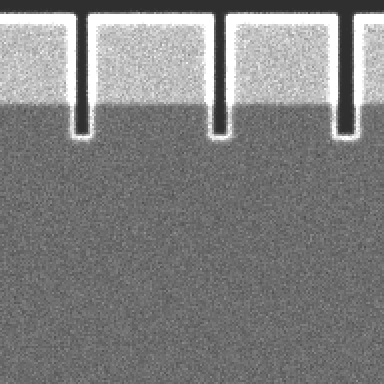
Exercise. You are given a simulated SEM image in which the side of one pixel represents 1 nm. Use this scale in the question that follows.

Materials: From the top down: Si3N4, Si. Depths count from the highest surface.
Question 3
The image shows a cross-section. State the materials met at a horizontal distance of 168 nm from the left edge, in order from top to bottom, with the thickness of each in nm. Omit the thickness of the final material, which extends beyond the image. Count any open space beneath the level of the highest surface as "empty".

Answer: Si3N4 88, Si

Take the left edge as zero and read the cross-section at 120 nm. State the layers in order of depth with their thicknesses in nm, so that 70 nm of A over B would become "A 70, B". Si3N4 88, Si